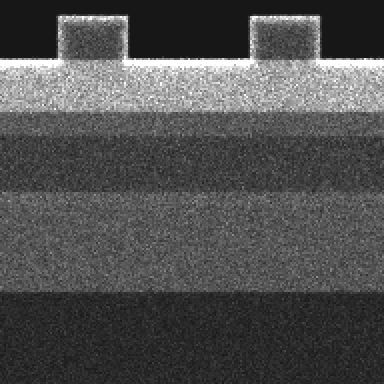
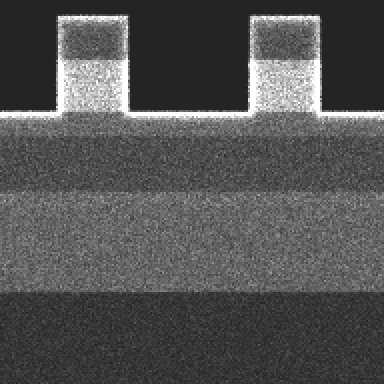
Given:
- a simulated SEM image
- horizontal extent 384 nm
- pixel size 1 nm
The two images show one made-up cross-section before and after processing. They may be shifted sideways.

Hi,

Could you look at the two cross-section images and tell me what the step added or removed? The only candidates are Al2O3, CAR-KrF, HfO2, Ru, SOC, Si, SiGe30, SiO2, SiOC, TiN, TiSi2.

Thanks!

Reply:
removed HfO2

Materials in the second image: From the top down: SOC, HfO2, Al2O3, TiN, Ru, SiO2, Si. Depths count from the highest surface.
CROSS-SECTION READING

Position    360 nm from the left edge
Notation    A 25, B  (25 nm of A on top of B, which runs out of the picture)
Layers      empty 96, Al2O3 24, TiN 56, Ru 14, SiO2 86, Si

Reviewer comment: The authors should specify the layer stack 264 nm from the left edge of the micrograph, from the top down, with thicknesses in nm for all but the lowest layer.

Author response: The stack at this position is SOC 44, HfO2 52, Al2O3 24, TiN 56, Ru 14, SiO2 86, Si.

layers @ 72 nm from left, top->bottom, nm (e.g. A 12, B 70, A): SOC 44, HfO2 52, Al2O3 24, TiN 56, Ru 14, SiO2 86, Si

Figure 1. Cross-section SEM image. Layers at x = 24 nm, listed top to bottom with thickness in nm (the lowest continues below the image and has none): empty 96, Al2O3 24, TiN 56, Ru 14, SiO2 86, Si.